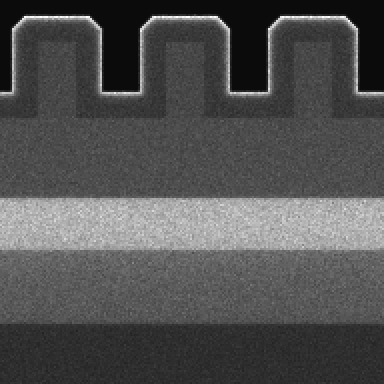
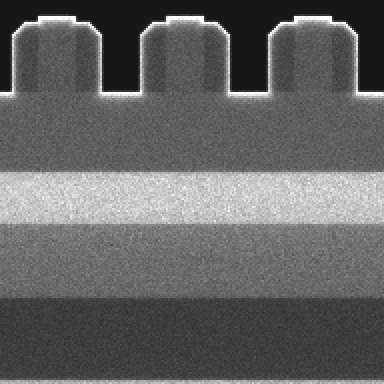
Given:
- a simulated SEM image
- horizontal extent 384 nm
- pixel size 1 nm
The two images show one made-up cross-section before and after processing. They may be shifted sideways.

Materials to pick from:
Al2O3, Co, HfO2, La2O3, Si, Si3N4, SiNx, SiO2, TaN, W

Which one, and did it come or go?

Si3N4 - removed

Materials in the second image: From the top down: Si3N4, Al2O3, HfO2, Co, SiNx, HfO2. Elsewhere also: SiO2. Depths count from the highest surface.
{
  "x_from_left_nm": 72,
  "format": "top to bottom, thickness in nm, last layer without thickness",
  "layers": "SiO2 76, Al2O3 80, HfO2 52, Co 74, SiNx 82, HfO2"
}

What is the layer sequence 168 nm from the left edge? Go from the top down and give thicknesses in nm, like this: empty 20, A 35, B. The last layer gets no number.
SiO2 76, Al2O3 80, HfO2 52, Co 74, SiNx 82, HfO2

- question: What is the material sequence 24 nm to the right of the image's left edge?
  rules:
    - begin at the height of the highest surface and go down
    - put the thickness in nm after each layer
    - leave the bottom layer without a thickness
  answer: empty 6, Si3N4 70, Al2O3 80, HfO2 52, Co 74, SiNx 82, HfO2